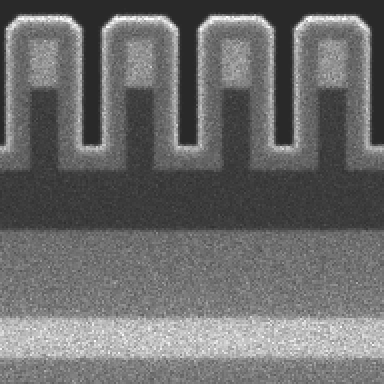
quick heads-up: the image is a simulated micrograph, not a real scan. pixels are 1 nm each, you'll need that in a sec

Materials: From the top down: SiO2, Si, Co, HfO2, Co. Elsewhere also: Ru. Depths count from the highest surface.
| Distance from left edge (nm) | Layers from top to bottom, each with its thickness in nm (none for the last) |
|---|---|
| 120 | SiO2 154, Si 60, Co 88, HfO2 40, Co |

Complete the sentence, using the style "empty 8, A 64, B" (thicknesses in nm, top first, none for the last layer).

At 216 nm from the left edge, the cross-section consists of SiO2 154, Si 60, Co 88, HfO2 40, Co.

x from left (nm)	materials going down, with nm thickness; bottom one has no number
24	SiO2 154, Si 60, Co 88, HfO2 40, Co